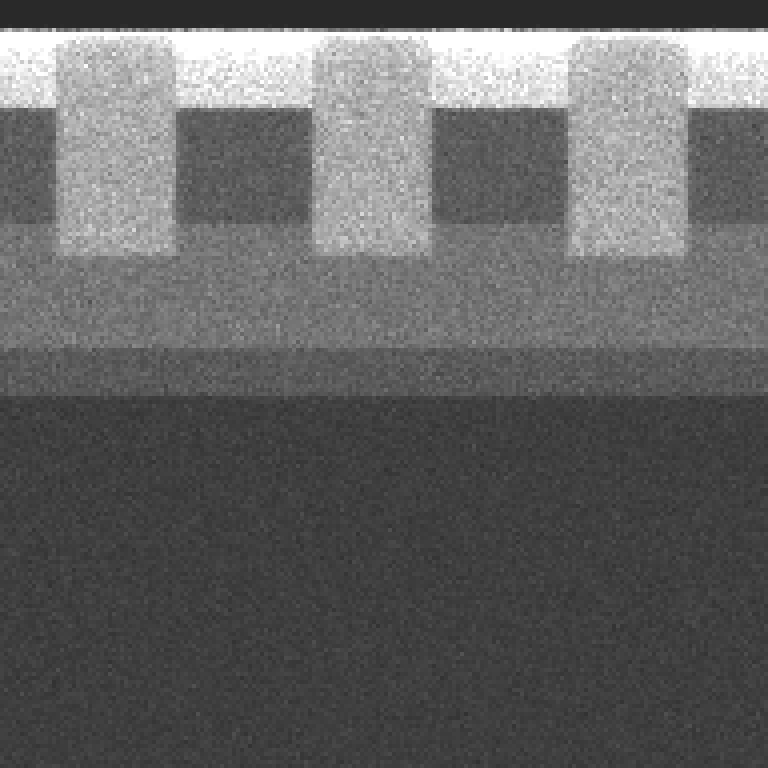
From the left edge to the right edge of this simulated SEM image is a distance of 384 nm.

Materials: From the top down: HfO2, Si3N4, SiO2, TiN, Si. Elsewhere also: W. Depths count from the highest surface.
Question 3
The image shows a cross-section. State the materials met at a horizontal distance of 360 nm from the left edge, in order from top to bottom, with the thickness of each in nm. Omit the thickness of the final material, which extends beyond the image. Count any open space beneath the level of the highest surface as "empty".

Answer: HfO2 38, Si3N4 58, SiO2 62, TiN 24, Si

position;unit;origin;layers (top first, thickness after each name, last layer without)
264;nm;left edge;HfO2 38, Si3N4 58, SiO2 62, TiN 24, Si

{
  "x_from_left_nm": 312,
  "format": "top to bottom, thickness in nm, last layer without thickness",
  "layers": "W 112, SiO2 46, TiN 24, Si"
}